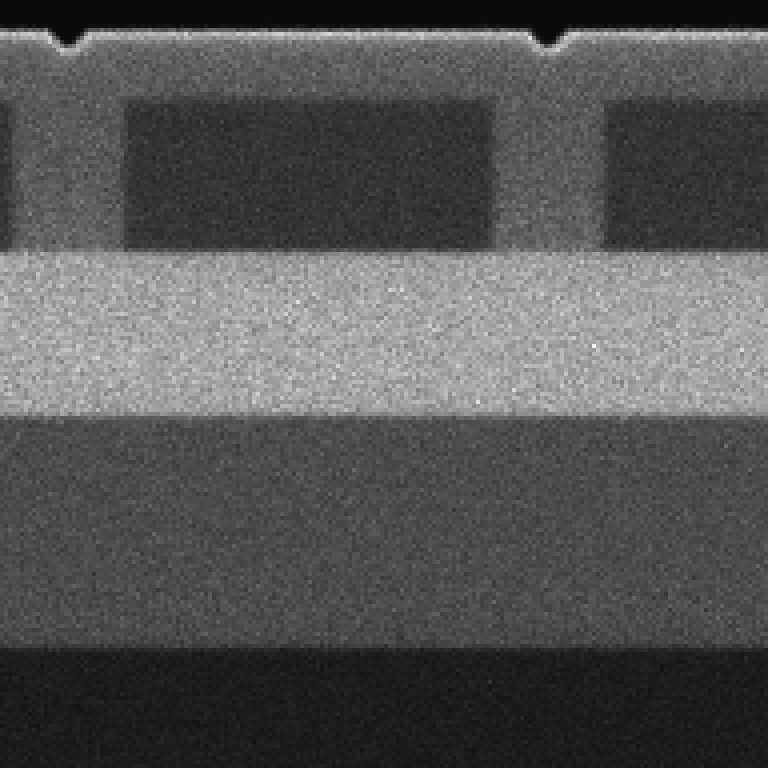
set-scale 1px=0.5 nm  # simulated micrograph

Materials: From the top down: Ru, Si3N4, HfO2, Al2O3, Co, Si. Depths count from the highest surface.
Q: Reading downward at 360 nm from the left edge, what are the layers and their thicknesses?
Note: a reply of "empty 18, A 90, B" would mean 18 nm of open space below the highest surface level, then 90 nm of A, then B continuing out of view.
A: Ru 34, Si3N4 76, HfO2 82, Al2O3 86, Co 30, Si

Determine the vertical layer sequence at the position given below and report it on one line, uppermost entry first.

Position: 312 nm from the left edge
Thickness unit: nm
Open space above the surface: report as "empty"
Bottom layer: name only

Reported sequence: Ru 34, Si3N4 76, HfO2 82, Al2O3 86, Co 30, Si